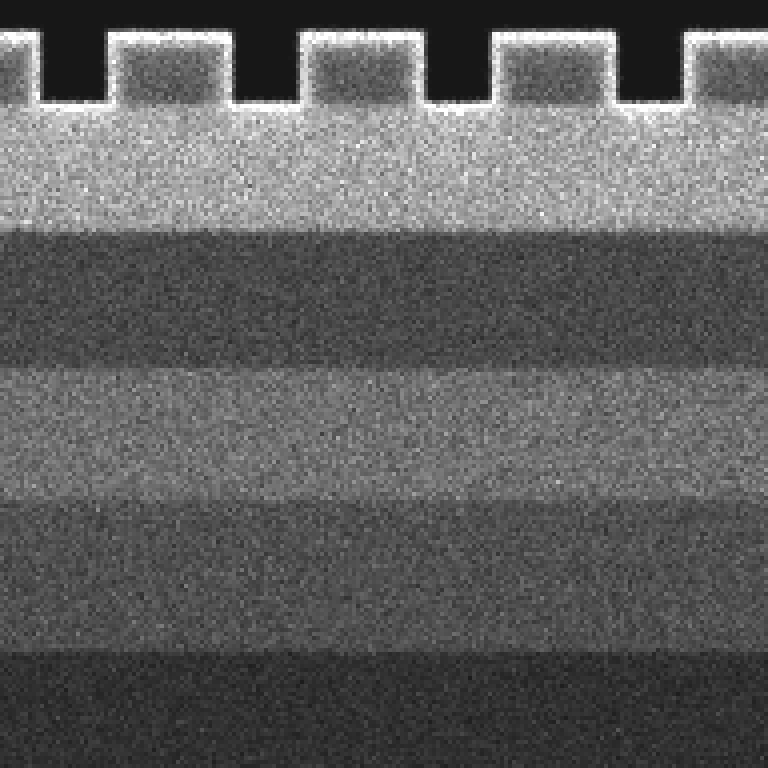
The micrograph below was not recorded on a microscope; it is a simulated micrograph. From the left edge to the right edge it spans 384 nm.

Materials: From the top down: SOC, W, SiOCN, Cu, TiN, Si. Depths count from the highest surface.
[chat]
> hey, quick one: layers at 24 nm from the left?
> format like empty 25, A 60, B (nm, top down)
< empty 36, W 64, SiOCN 68, Cu 66, TiN 76, Si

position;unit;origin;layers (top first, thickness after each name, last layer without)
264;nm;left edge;SOC 36, W 64, SiOCN 68, Cu 66, TiN 76, Si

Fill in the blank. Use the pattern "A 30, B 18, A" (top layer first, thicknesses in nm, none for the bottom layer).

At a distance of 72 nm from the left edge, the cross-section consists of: SOC 36, W 64, SiOCN 68, Cu 66, TiN 76, Si